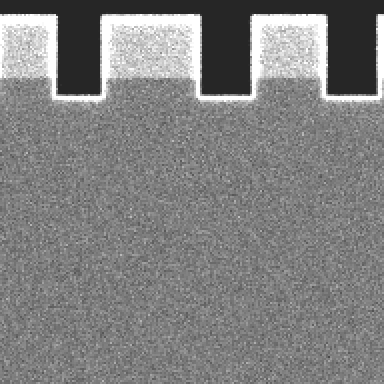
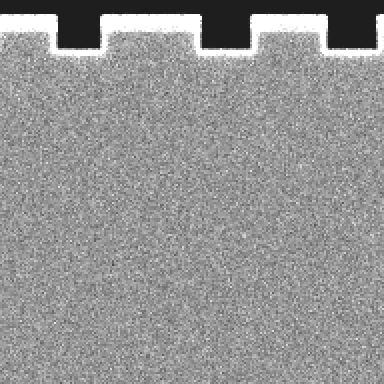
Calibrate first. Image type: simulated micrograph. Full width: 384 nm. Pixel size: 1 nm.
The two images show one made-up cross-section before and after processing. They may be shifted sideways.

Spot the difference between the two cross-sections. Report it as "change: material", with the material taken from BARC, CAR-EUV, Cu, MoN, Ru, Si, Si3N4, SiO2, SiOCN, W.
removed: SiOCN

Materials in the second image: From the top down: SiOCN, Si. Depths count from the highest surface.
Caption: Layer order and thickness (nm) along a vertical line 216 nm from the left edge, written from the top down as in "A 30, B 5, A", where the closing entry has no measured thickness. empty 34, Si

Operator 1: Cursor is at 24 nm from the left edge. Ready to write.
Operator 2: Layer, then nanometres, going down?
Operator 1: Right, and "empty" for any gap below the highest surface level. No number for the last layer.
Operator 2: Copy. SiOCN 16, Si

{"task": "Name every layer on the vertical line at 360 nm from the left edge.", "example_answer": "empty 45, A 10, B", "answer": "empty 34, Si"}